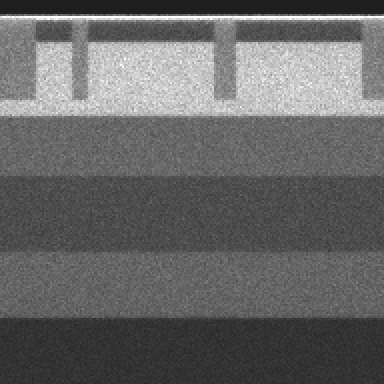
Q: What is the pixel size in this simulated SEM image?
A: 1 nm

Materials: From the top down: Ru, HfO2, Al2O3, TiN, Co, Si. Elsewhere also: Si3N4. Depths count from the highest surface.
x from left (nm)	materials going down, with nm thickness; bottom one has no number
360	Si3N4 26, HfO2 74, Al2O3 60, TiN 76, Co 66, Si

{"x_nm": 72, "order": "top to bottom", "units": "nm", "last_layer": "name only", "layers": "Ru 84, HfO2 16, Al2O3 60, TiN 76, Co 66, Si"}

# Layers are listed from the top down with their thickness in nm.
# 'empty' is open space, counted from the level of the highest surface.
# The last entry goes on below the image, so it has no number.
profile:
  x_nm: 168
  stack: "Si3N4 26, HfO2 74, Al2O3 60, TiN 76, Co 66, Si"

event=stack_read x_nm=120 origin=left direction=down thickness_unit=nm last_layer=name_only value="Si3N4 26, HfO2 74, Al2O3 60, TiN 76, Co 66, Si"